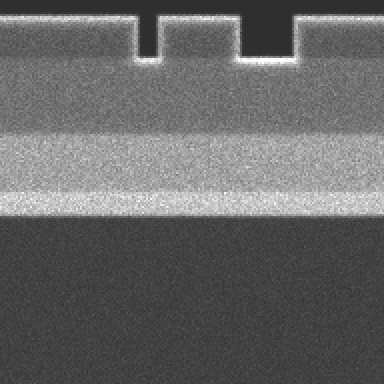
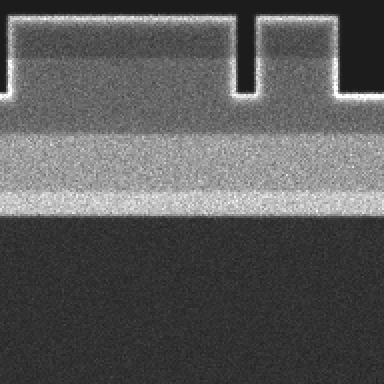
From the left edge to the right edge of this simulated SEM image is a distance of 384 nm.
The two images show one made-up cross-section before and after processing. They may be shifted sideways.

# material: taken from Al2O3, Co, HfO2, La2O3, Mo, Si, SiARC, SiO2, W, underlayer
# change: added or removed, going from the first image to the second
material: SiO2
change: removed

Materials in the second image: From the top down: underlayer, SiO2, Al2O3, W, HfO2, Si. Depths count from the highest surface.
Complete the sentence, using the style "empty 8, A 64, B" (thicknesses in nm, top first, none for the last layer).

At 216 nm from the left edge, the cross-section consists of underlayer 42, SiO2 64, Al2O3 12, W 58, HfO2 24, Si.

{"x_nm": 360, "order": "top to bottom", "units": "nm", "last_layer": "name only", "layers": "empty 78, SiO2 28, Al2O3 12, W 58, HfO2 24, Si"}